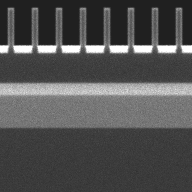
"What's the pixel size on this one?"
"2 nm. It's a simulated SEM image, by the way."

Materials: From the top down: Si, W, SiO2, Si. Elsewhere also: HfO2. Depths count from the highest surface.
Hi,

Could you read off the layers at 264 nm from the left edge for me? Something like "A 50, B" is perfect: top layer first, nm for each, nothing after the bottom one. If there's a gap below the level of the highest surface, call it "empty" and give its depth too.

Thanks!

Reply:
Si 150, W 24, SiO2 66, Si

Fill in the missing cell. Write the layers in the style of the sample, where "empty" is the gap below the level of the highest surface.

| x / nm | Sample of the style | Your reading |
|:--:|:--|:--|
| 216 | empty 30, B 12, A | Si 150, W 24, SiO2 66, Si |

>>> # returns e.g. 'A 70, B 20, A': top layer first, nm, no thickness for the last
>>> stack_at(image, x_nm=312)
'Si 150, W 24, SiO2 66, Si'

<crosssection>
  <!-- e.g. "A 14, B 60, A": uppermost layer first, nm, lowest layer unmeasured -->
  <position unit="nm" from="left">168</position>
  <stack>Si 150, W 24, SiO2 66, Si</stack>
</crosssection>